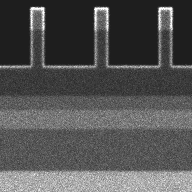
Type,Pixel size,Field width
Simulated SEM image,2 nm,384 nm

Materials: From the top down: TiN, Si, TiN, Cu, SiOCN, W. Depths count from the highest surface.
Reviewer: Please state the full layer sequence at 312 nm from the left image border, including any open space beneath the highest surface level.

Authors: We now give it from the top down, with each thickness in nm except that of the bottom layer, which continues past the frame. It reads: empty 116, Si 60, TiN 28, Cu 38, SiOCN 84, W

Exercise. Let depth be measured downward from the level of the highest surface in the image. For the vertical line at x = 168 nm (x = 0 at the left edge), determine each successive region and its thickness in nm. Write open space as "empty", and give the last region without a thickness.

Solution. empty 116, Si 60, TiN 28, Cu 38, SiOCN 84, W